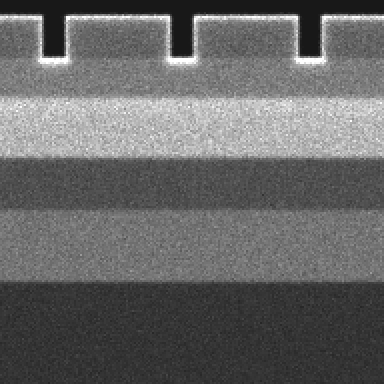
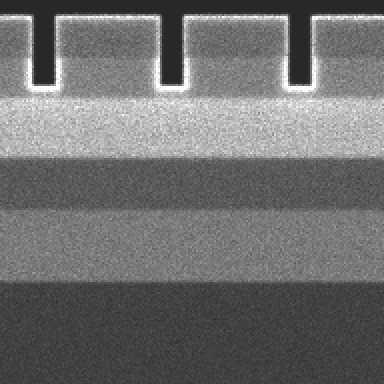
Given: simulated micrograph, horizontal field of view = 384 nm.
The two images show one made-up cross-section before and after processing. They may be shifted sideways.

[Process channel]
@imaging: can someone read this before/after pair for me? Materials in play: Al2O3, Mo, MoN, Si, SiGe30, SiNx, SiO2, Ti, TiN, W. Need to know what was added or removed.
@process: Al2O3 removed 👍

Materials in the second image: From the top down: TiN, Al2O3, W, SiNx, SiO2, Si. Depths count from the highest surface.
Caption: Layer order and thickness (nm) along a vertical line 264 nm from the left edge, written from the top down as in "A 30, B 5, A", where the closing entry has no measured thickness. TiN 42, Al2O3 40, W 60, SiNx 52, SiO2 72, Si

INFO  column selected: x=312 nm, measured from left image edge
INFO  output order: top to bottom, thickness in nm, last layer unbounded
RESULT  TiN 42, Al2O3 40, W 60, SiNx 52, SiO2 72, Si